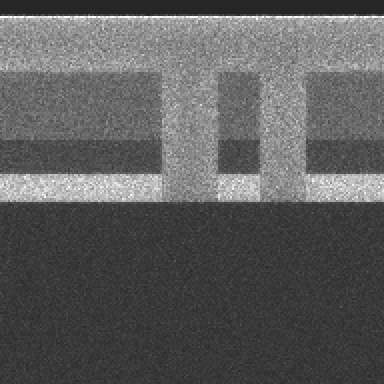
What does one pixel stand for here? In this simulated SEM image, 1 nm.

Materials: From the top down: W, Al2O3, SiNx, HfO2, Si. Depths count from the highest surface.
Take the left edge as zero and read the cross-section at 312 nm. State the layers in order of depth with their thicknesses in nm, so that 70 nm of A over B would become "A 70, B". W 56, Al2O3 68, SiNx 34, HfO2 28, Si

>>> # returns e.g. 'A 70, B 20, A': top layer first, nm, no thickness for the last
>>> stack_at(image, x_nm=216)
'W 186, Si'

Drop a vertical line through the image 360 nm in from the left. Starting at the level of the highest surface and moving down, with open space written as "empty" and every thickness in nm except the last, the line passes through W 56, Al2O3 68, SiNx 34, HfO2 28, Si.